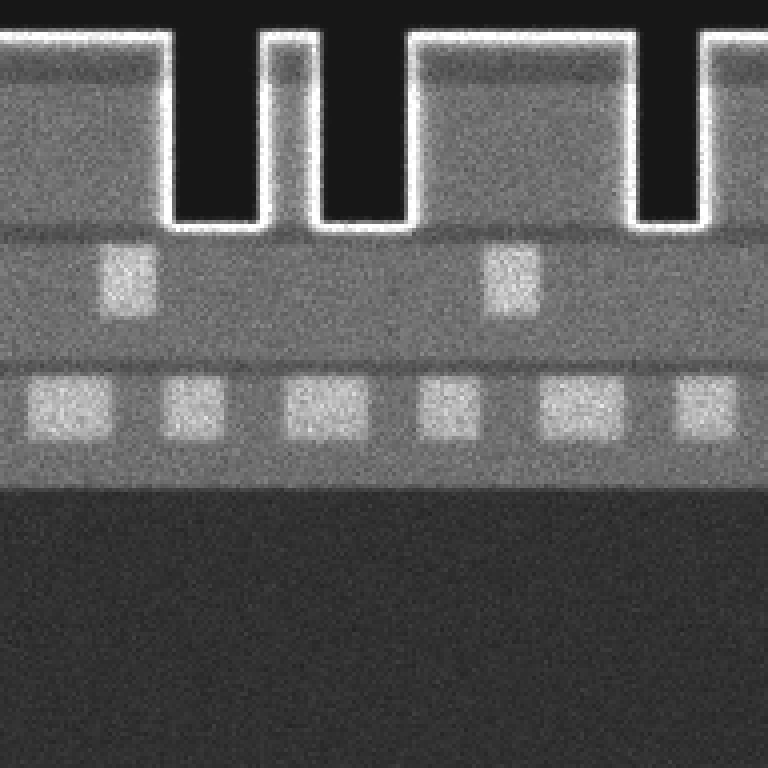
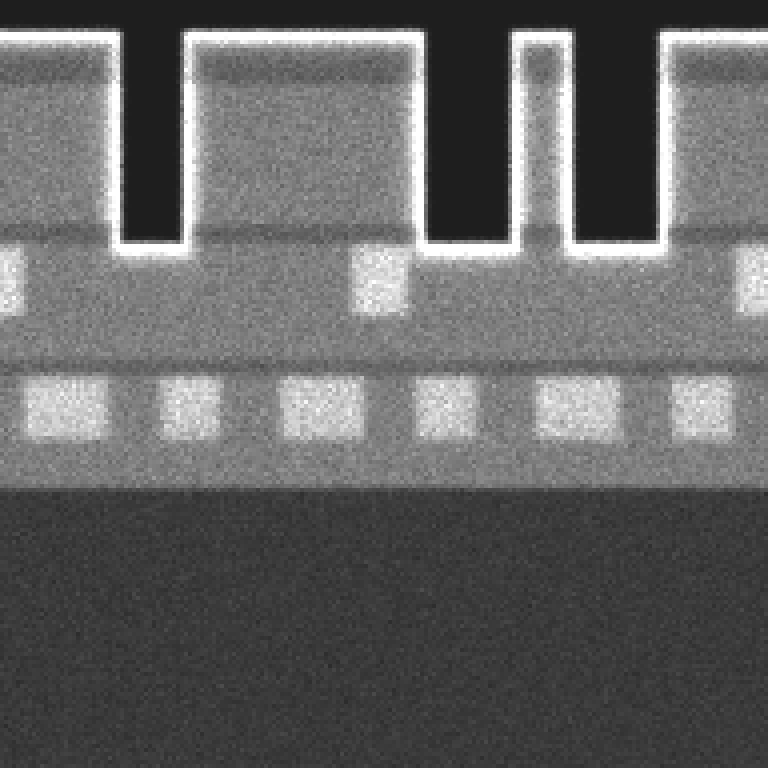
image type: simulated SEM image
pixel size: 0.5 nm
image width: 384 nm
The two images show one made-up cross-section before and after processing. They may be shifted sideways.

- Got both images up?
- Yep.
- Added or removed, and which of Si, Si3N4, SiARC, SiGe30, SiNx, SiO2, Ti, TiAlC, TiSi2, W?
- removed, Si3N4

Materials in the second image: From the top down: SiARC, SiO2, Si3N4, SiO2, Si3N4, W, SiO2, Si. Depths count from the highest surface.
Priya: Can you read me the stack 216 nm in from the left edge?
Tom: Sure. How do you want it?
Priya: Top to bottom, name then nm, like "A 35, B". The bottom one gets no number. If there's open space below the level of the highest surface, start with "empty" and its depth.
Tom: empty 106, SiO2 58, Si3N4 8, W 32, SiO2 24, Si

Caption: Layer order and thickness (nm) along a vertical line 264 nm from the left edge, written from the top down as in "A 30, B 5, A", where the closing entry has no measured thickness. SiARC 26, SiO2 70, Si3N4 10, SiO2 58, Si3N4 8, SiO2 56, Si